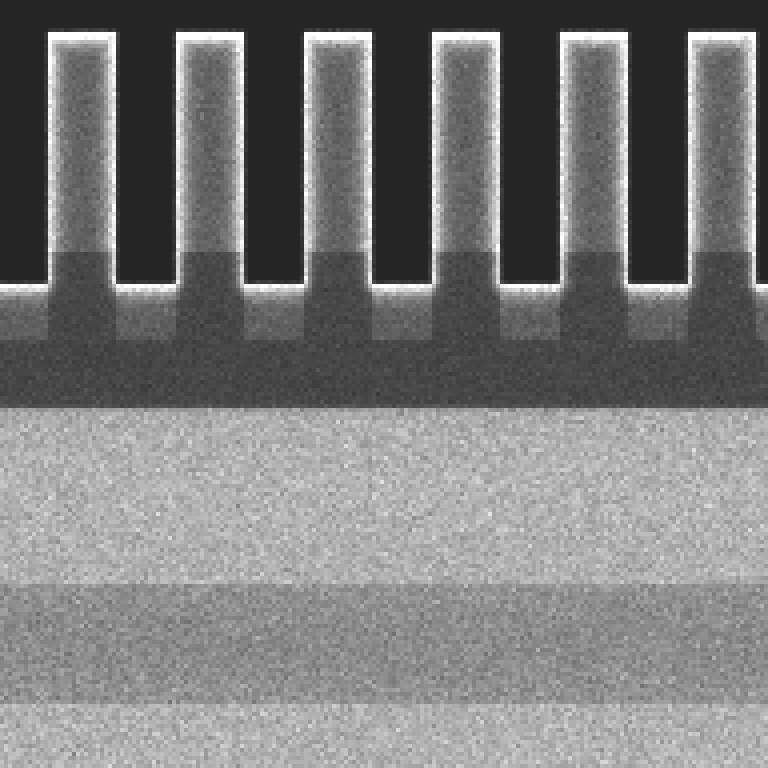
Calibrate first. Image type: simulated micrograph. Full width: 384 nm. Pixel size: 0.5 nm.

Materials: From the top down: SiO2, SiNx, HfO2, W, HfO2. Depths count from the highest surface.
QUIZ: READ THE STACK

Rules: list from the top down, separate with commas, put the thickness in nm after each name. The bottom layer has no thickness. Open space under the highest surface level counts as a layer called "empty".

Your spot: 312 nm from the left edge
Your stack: SiO2 110, SiNx 78, HfO2 88, W 60, HfO2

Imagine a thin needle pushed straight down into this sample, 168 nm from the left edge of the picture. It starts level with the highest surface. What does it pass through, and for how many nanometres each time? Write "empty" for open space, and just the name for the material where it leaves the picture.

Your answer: SiO2 110, SiNx 78, HfO2 88, W 60, HfO2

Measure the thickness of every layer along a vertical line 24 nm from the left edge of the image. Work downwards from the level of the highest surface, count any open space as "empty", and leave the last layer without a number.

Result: SiO2 110, SiNx 78, HfO2 88, W 60, HfO2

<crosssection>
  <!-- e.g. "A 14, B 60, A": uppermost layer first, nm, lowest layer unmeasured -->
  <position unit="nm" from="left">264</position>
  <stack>empty 126, SiO2 28, SiNx 34, HfO2 88, W 60, HfO2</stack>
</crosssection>